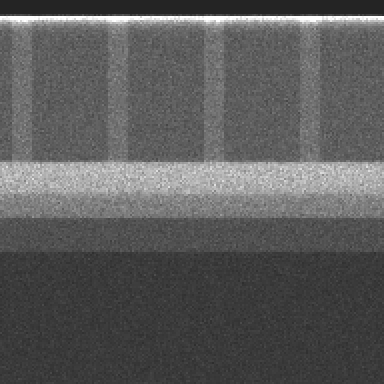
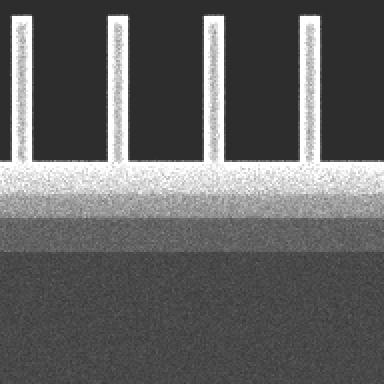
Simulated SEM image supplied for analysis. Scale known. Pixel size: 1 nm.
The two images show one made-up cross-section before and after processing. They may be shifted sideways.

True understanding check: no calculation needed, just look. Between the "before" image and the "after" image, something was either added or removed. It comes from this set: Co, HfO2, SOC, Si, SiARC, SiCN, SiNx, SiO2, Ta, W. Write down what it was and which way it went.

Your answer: SOC (removed)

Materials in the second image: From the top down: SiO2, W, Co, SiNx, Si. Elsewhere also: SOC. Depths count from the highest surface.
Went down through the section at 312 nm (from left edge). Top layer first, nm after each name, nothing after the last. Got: SiO2 146, W 32, Co 24, SiNx 34, Si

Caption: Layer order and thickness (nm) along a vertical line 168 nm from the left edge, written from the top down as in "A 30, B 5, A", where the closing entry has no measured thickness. empty 146, W 32, Co 24, SiNx 34, Si